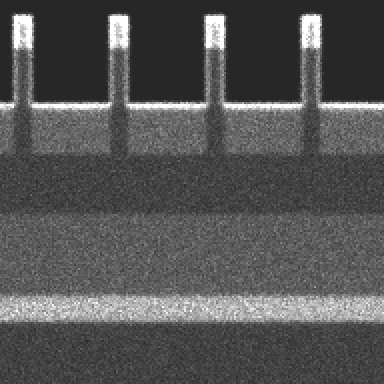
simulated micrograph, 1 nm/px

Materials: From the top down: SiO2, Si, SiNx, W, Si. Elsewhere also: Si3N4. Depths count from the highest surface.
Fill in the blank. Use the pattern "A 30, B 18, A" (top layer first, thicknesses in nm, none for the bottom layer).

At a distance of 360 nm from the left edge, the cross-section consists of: empty 88, Si3N4 50, Si 60, SiNx 82, W 26, Si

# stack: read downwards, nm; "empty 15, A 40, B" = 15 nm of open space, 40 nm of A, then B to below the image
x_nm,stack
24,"SiO2 32, Si 166, SiNx 82, W 26, Si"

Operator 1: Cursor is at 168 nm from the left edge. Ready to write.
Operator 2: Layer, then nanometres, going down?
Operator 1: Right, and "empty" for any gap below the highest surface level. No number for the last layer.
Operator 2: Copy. empty 88, Si3N4 50, Si 60, SiNx 82, W 26, Si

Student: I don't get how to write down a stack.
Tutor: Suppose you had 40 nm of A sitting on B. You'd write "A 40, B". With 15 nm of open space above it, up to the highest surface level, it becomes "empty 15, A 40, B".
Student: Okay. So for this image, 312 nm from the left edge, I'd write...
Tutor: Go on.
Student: SiO2 32, Si 166, SiNx 82, W 26, Si